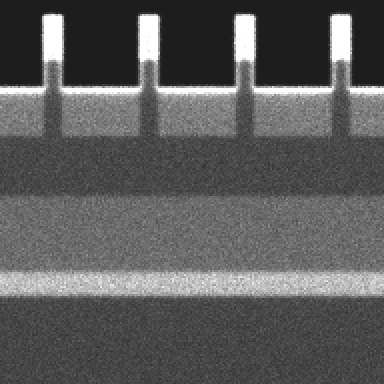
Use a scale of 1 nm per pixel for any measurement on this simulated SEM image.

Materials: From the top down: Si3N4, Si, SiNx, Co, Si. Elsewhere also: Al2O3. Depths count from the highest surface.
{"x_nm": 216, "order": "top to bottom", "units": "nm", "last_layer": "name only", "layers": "empty 72, Si3N4 48, Si 60, SiNx 76, Co 24, Si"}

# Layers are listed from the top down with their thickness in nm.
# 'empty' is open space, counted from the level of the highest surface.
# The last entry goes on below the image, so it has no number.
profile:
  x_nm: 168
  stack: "empty 72, Si3N4 48, Si 60, SiNx 76, Co 24, Si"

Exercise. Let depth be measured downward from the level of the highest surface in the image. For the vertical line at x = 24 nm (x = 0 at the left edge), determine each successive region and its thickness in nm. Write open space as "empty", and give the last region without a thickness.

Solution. empty 72, Si3N4 48, Si 60, SiNx 76, Co 24, Si